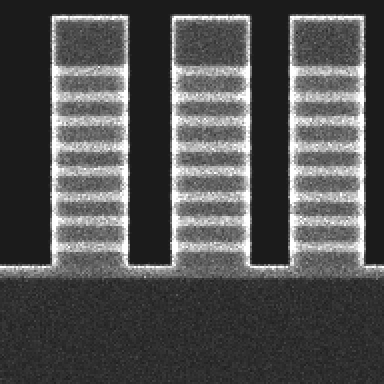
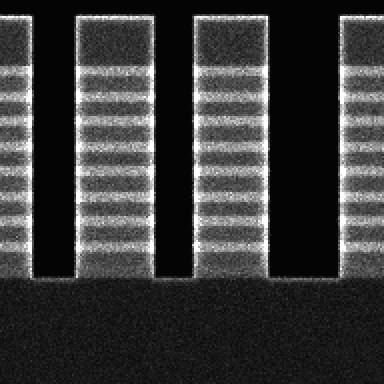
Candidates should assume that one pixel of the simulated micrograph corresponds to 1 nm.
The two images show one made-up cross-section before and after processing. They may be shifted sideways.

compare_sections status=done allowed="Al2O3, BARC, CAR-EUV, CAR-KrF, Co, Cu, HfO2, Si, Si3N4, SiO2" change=removed material="Co"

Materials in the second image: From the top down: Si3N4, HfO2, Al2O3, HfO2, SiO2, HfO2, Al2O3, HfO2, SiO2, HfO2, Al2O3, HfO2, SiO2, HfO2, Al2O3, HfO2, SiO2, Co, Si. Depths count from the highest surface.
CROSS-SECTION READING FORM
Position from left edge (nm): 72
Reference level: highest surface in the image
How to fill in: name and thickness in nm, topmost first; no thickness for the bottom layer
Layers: empty 262, Si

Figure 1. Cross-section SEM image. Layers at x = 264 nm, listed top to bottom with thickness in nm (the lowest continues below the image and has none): Si3N4 50, HfO2 10, Al2O3 16, HfO2 10, SiO2 14, HfO2 10, Al2O3 16, HfO2 10, SiO2 14, HfO2 10, Al2O3 16, HfO2 10, SiO2 14, HfO2 10, Al2O3 16, HfO2 10, SiO2 14, Co 12, Si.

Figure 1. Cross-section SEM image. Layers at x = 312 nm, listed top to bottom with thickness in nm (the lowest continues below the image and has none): empty 262, Si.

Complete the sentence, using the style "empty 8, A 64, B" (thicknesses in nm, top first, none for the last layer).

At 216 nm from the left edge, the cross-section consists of Si3N4 50, HfO2 10, Al2O3 16, HfO2 10, SiO2 14, HfO2 10, Al2O3 16, HfO2 10, SiO2 14, HfO2 10, Al2O3 16, HfO2 10, SiO2 14, HfO2 10, Al2O3 16, HfO2 10, SiO2 14, Co 12, Si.